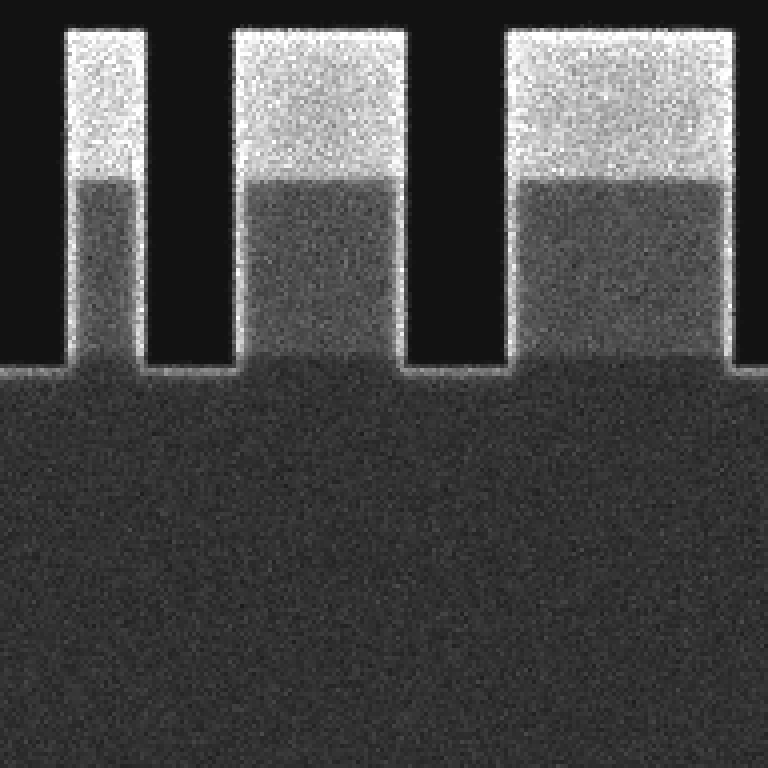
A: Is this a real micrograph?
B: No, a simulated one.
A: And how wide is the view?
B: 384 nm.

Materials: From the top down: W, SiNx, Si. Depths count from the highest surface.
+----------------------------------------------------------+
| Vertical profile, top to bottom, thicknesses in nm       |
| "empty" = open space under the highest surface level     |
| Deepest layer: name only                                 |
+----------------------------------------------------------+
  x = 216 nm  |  empty 168, Si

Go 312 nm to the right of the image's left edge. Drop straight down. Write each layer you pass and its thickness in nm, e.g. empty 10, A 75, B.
W 74, SiNx 88, Si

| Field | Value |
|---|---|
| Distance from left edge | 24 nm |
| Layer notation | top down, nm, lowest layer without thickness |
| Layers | empty 168, Si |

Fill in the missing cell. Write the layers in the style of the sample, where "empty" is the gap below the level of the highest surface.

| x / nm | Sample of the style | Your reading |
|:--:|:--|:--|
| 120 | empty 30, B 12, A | W 74, SiNx 88, Si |